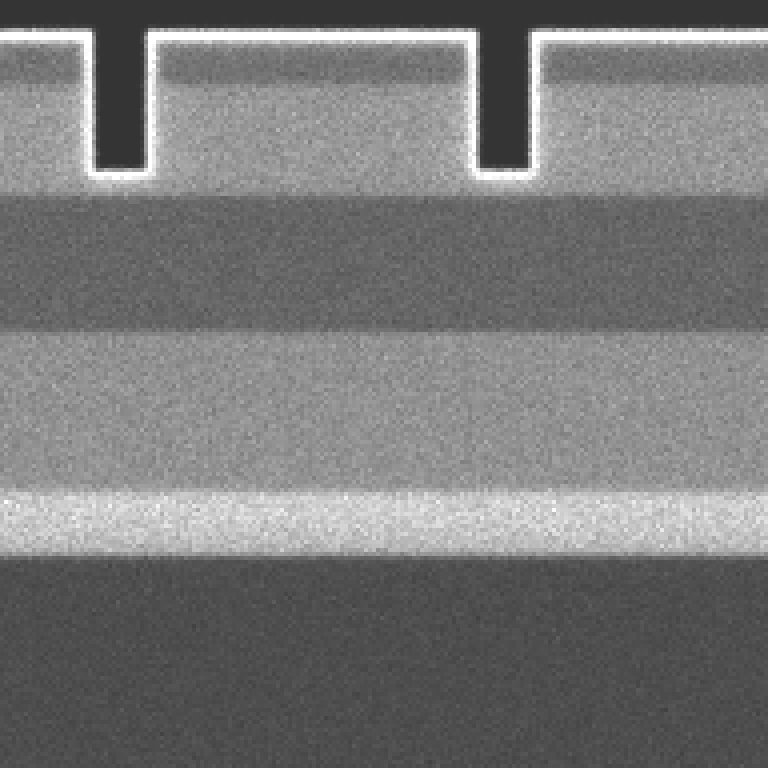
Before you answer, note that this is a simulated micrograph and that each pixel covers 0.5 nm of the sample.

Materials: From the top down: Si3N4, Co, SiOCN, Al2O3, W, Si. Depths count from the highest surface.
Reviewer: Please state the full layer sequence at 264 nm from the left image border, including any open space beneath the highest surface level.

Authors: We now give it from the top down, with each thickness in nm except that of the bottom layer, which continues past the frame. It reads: empty 70, Co 12, SiOCN 68, Al2O3 80, W 32, Si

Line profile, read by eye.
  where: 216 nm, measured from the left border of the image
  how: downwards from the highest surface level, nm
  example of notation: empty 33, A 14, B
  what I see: Si3N4 26, Co 56, SiOCN 68, Al2O3 80, W 32, Si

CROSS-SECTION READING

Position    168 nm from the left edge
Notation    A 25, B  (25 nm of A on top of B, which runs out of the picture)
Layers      Si3N4 26, Co 56, SiOCN 68, Al2O3 80, W 32, Si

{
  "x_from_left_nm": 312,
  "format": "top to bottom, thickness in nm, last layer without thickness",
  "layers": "Si3N4 26, Co 56, SiOCN 68, Al2O3 80, W 32, Si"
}